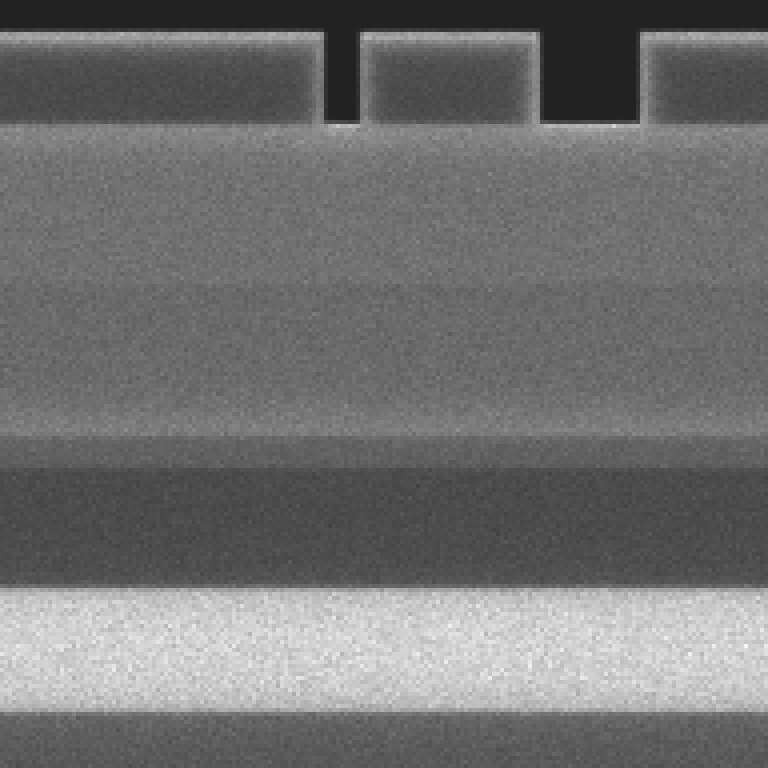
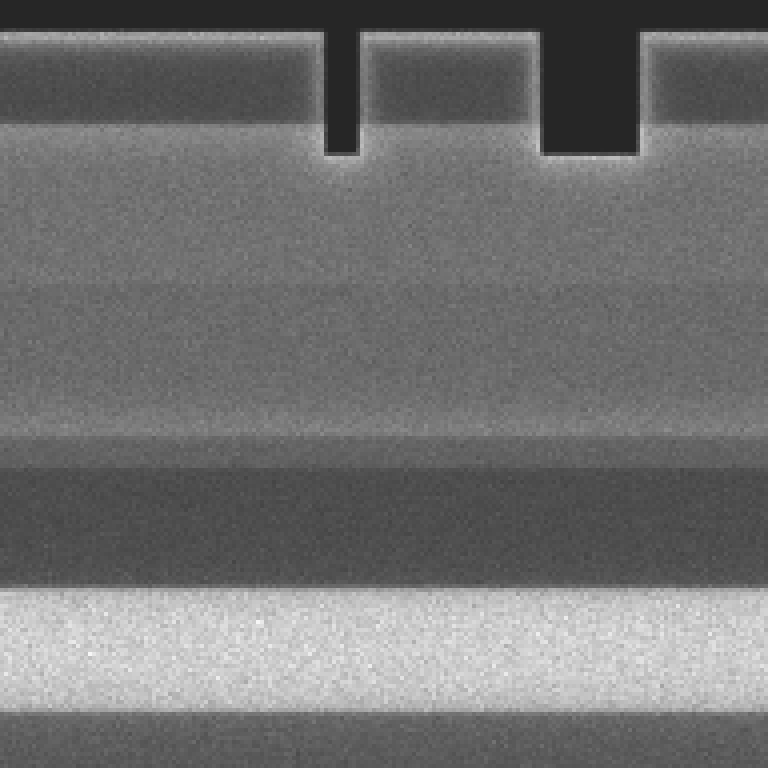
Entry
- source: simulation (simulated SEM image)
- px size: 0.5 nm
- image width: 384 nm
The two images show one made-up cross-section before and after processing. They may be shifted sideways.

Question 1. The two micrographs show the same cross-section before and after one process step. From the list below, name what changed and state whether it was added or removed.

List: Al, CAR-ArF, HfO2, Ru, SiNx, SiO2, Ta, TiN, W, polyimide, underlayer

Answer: W, removed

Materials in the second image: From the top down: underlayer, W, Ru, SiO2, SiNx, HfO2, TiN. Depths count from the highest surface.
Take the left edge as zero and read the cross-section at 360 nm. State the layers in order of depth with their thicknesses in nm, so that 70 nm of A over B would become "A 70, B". underlayer 46, W 80, Ru 76, SiO2 16, SiNx 60, HfO2 62, TiN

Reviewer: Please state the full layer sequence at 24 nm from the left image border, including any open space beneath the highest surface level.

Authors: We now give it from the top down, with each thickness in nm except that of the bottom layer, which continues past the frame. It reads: underlayer 46, W 80, Ru 76, SiO2 16, SiNx 60, HfO2 62, TiN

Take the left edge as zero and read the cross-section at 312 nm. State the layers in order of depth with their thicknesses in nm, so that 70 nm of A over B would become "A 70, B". empty 62, W 64, Ru 76, SiO2 16, SiNx 60, HfO2 62, TiN